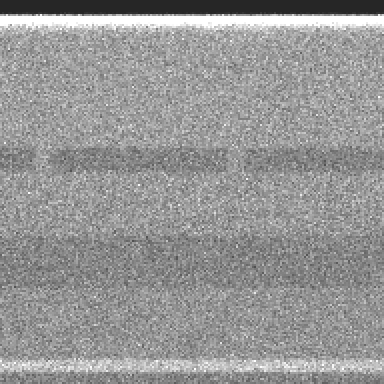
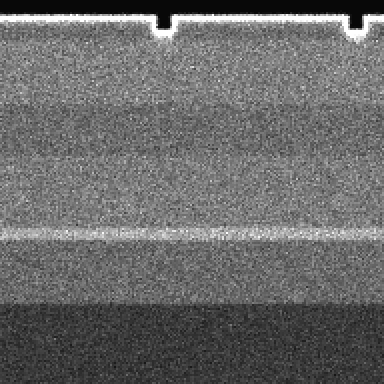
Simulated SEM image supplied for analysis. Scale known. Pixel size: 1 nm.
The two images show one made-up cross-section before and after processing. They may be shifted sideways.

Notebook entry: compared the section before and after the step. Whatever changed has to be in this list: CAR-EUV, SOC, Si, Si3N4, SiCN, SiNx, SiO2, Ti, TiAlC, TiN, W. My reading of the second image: SOC removed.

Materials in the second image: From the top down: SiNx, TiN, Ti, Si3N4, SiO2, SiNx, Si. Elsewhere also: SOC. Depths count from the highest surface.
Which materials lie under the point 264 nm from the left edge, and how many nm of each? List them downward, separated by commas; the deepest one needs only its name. SiNx 24, TiN 64, Ti 52, Si3N4 72, SiO2 12, SiNx 64, Si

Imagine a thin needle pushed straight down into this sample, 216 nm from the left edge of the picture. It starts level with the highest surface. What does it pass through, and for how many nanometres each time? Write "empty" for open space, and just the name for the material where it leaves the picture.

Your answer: SiNx 24, TiN 64, Ti 52, Si3N4 72, SiO2 12, SiNx 64, Si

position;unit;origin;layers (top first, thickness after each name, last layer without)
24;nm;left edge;SiNx 24, TiN 64, Ti 52, Si3N4 72, SiO2 12, SiNx 64, Si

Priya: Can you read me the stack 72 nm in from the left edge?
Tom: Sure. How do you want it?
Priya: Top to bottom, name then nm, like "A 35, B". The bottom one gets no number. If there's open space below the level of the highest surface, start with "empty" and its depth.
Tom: SiNx 24, TiN 64, Ti 52, Si3N4 72, SiO2 12, SiNx 64, Si